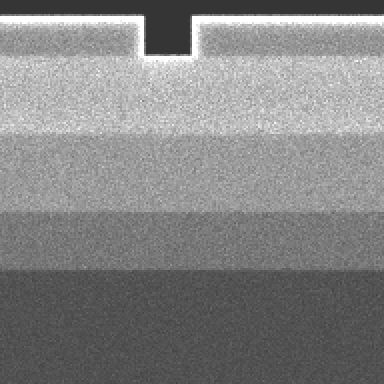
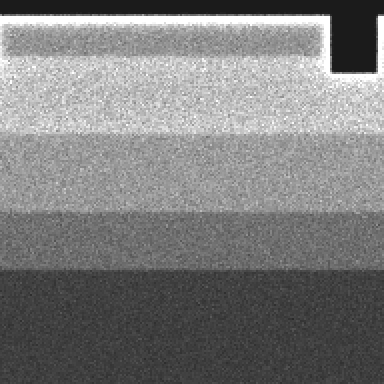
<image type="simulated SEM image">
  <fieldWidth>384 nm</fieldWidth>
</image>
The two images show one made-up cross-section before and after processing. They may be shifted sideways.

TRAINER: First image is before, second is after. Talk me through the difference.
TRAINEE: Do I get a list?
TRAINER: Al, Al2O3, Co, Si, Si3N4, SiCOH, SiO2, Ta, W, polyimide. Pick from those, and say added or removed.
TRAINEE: removed: Co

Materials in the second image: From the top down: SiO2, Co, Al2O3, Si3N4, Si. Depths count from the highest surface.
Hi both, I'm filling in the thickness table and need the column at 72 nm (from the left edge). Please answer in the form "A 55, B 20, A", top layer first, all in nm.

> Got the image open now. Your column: SiO2 40, Co 78, Al2O3 78, Si3N4 58, Si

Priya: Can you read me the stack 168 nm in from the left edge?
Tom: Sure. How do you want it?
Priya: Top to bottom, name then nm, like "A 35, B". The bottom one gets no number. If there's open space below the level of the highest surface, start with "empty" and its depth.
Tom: SiO2 40, Co 78, Al2O3 78, Si3N4 58, Si